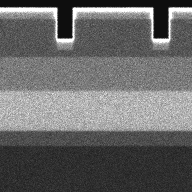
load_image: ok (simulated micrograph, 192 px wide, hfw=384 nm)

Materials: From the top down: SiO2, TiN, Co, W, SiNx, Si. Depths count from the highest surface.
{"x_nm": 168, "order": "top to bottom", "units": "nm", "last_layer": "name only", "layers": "SiO2 22, TiN 76, Co 68, W 80, SiNx 30, Si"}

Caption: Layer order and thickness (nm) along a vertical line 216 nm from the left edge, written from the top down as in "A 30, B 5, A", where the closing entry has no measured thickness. SiO2 22, TiN 76, Co 68, W 80, SiNx 30, Si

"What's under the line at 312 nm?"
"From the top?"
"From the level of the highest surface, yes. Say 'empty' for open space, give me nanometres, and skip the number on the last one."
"empty 62, SiO2 22, TiN 14, Co 68, W 80, SiNx 30, Si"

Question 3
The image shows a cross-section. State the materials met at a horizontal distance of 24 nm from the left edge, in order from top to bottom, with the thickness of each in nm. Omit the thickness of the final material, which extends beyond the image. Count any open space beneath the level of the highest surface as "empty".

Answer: SiO2 22, TiN 76, Co 68, W 80, SiNx 30, Si